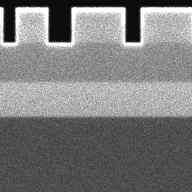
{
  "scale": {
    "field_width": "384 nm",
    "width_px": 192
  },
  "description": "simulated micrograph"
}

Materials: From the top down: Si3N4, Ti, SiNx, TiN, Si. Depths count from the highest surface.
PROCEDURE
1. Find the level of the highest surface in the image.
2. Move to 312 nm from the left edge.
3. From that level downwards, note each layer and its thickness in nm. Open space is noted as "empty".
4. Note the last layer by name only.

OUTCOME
Si3N4 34, Ti 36, SiNx 78, TiN 70, Si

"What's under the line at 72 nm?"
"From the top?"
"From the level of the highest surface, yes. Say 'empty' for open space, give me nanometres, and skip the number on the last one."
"Si3N4 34, Ti 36, SiNx 78, TiN 70, Si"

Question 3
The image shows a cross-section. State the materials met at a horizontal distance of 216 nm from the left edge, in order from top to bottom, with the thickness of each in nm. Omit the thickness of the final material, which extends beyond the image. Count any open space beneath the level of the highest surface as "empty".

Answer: Si3N4 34, Ti 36, SiNx 78, TiN 70, Si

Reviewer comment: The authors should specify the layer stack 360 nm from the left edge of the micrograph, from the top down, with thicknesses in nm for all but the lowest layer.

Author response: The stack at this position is Si3N4 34, Ti 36, SiNx 78, TiN 70, Si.